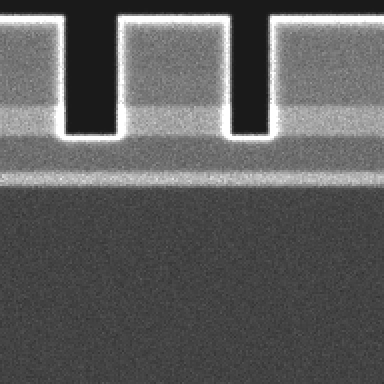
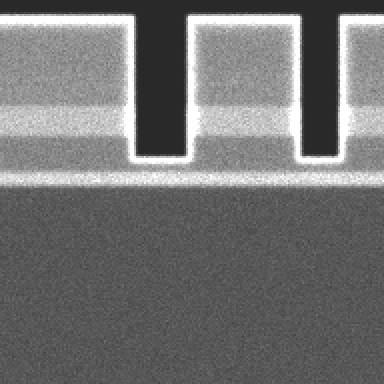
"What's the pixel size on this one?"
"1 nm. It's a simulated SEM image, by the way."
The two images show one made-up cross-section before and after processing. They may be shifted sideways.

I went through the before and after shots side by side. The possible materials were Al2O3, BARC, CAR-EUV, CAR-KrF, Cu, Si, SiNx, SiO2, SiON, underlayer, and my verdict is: removed, SiNx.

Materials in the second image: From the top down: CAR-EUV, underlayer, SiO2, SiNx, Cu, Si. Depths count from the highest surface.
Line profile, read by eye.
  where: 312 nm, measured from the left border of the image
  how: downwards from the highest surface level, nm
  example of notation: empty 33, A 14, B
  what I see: empty 142, SiNx 14, Cu 14, Si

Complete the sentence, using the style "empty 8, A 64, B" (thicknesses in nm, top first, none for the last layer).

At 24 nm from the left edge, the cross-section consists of CAR-EUV 56, underlayer 34, SiO2 30, SiNx 36, Cu 14, Si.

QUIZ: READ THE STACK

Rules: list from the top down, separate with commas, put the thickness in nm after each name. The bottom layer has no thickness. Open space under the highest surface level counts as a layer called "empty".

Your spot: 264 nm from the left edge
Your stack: CAR-EUV 56, underlayer 34, SiO2 30, SiNx 36, Cu 14, Si